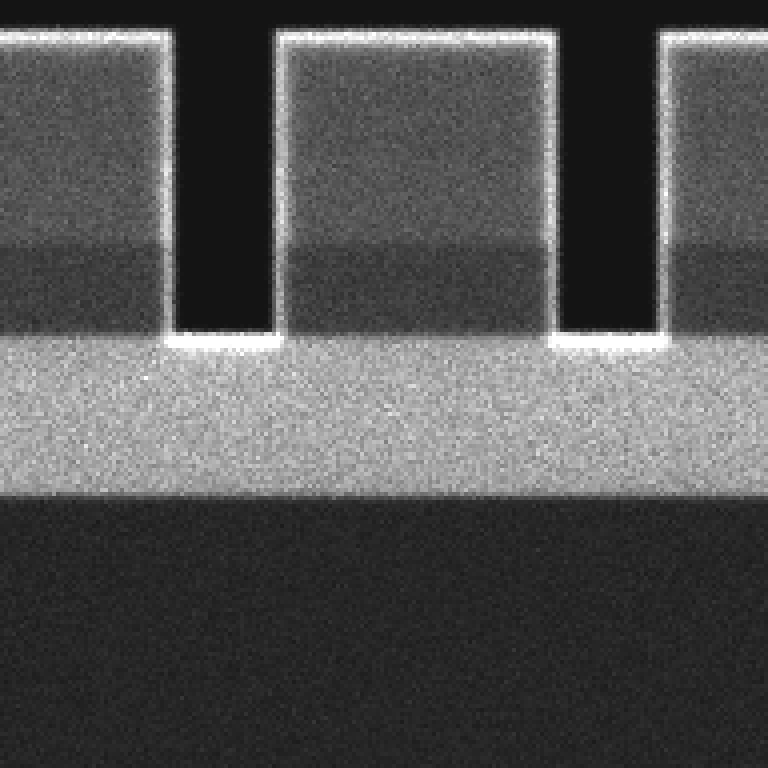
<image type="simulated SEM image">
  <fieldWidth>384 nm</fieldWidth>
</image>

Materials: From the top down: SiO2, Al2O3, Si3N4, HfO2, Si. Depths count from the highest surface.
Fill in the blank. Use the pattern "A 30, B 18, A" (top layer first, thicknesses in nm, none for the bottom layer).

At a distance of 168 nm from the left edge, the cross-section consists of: SiO2 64, Al2O3 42, Si3N4 46, HfO2 80, Si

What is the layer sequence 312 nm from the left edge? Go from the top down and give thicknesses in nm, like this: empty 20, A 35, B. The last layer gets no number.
empty 152, HfO2 80, Si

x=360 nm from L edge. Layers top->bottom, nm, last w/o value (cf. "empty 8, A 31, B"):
SiO2 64, Al2O3 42, Si3N4 46, HfO2 80, Si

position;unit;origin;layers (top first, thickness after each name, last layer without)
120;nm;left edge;empty 152, HfO2 80, Si